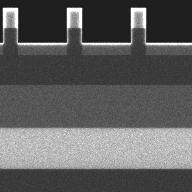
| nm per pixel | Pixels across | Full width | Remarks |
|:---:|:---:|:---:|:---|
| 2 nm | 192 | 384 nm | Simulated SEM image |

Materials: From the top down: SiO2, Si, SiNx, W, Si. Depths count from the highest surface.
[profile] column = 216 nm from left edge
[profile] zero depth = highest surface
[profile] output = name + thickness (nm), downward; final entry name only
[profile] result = empty 70, SiNx 24, Si 60, SiNx 86, W 82, Si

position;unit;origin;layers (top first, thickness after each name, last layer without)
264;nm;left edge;SiO2 40, Si 114, SiNx 86, W 82, Si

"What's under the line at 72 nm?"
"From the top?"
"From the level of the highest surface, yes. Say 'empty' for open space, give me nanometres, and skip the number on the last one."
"empty 70, SiNx 24, Si 60, SiNx 86, W 82, Si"